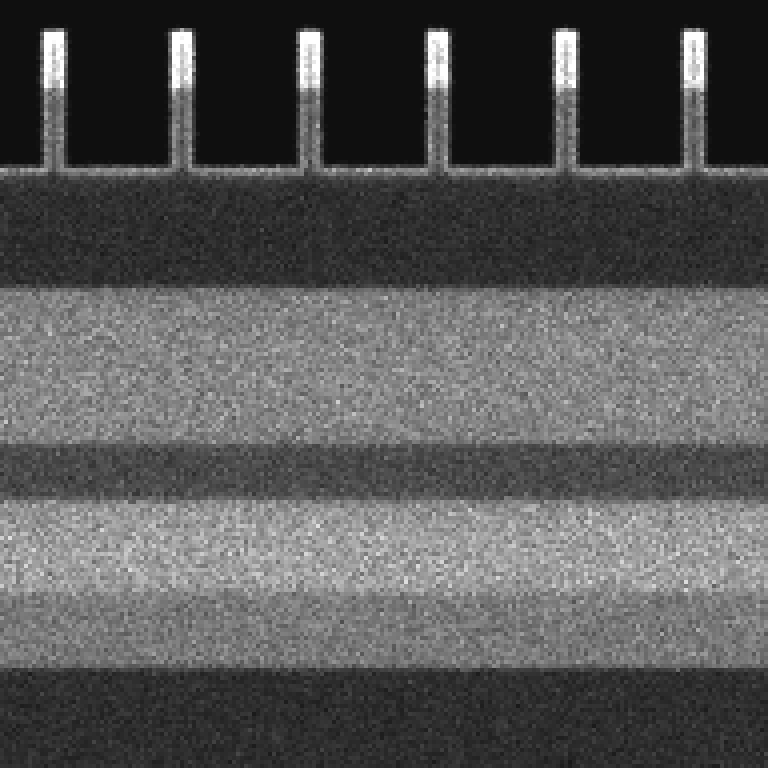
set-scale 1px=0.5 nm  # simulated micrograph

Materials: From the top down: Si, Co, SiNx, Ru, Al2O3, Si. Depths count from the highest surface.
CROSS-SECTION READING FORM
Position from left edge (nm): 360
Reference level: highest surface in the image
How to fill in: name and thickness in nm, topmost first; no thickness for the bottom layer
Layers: empty 68, Si 60, Co 78, SiNx 28, Ru 46, Al2O3 38, Si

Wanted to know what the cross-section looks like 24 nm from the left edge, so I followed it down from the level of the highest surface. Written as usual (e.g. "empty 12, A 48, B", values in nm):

Si 128, Co 78, SiNx 28, Ru 46, Al2O3 38, Si